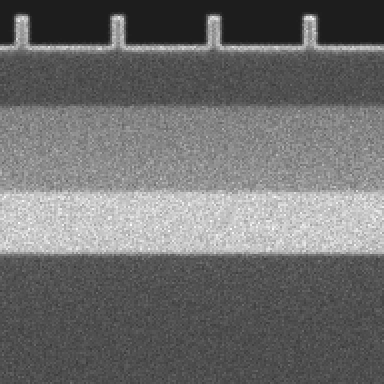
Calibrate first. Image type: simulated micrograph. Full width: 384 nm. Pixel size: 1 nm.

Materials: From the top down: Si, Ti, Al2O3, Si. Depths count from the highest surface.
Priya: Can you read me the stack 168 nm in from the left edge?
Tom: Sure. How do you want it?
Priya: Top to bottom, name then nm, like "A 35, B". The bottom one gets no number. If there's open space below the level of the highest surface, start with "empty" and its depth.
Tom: empty 30, Si 60, Ti 86, Al2O3 62, Si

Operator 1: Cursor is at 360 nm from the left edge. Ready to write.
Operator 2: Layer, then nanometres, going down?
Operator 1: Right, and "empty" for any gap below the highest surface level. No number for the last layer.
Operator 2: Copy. empty 30, Si 60, Ti 86, Al2O3 62, Si